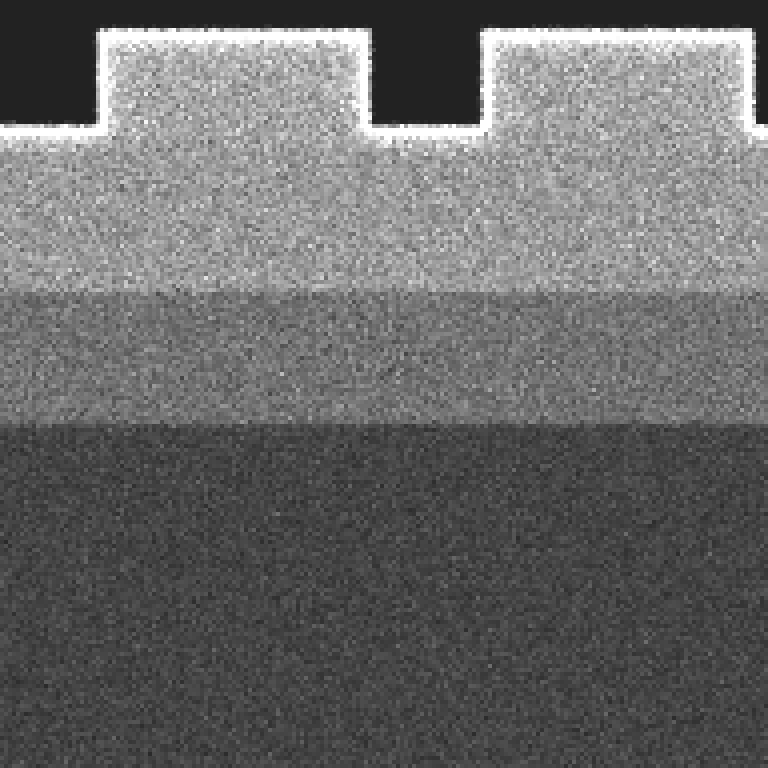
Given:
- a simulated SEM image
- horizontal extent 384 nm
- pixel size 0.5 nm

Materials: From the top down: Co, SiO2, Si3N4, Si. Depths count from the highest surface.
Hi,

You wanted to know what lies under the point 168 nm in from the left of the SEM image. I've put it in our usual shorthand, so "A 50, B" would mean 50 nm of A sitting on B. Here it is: Co 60, SiO2 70, Si3N4 66, Si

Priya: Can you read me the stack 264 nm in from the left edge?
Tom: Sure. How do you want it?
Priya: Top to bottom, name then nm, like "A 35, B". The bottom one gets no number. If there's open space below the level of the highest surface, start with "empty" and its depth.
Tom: Co 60, SiO2 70, Si3N4 66, Si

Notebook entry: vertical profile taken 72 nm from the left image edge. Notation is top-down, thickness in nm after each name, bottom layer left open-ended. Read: Co 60, SiO2 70, Si3N4 66, Si